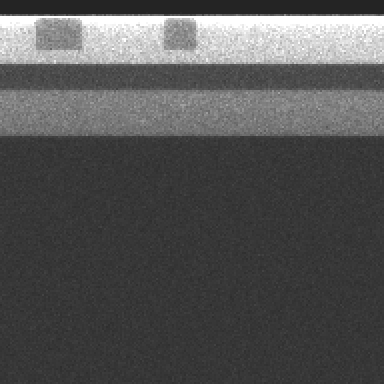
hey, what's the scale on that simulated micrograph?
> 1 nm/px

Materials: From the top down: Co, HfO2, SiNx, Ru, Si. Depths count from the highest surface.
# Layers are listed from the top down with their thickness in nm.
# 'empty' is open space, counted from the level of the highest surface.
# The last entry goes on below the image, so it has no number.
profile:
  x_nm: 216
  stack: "HfO2 48, SiNx 26, Ru 46, Si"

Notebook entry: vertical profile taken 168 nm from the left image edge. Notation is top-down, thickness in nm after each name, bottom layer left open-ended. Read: Co 34, HfO2 14, SiNx 26, Ru 46, Si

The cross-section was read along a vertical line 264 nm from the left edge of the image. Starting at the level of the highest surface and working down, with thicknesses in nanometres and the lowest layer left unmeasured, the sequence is HfO2 48, SiNx 26, Ru 46, Si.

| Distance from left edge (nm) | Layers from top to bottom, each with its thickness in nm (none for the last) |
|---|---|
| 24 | HfO2 48, SiNx 26, Ru 46, Si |